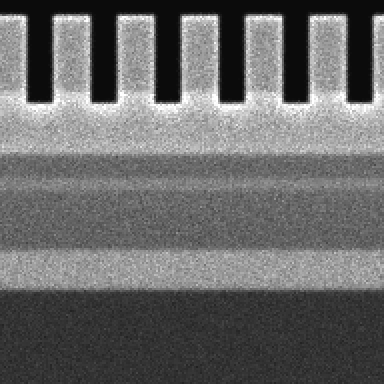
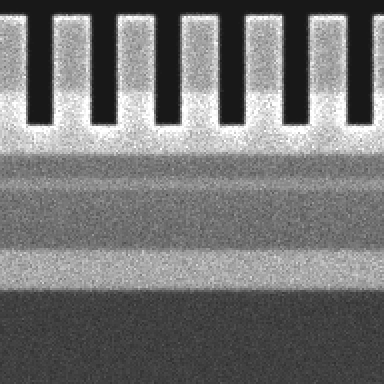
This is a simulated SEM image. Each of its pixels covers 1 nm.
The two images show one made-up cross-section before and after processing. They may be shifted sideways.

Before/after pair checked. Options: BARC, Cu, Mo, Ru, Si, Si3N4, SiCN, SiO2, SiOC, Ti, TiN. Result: removed Ru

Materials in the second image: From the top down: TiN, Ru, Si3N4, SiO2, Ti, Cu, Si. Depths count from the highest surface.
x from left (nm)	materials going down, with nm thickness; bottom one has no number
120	TiN 76, Ru 62, Si3N4 24, SiO2 12, Ti 60, Cu 40, Si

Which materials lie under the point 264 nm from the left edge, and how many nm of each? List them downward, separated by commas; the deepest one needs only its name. TiN 76, Ru 62, Si3N4 24, SiO2 12, Ti 60, Cu 40, Si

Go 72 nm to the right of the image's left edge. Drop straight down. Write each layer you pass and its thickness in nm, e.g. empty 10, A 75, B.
TiN 76, Ru 62, Si3N4 24, SiO2 12, Ti 60, Cu 40, Si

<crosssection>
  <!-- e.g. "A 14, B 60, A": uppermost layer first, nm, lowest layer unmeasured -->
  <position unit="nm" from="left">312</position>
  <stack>TiN 76, Ru 62, Si3N4 24, SiO2 12, Ti 60, Cu 40, Si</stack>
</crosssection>